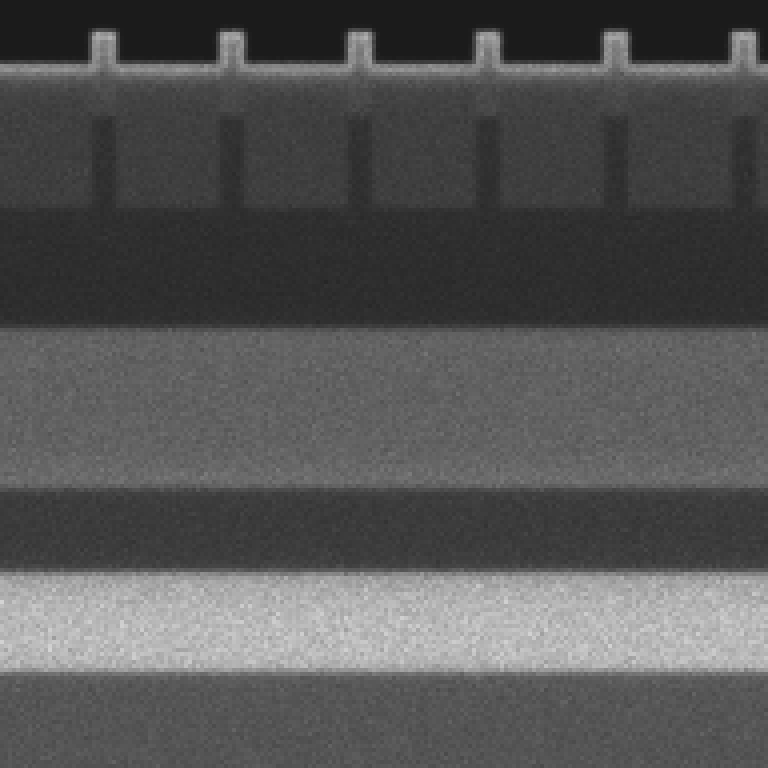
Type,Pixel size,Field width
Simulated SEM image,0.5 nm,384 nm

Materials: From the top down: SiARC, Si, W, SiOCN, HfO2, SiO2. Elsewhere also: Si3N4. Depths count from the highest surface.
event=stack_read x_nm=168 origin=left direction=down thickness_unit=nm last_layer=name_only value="empty 16, SiARC 72, Si 60, W 80, SiOCN 42, HfO2 50, SiO2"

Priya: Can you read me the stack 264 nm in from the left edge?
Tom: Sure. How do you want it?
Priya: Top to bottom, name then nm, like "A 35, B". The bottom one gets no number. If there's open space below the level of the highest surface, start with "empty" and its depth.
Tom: empty 16, SiARC 72, Si 60, W 80, SiOCN 42, HfO2 50, SiO2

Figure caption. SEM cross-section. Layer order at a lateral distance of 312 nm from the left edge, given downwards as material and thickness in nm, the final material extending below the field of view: Si3N4 42, Si 106, W 80, SiOCN 42, HfO2 50, SiO2